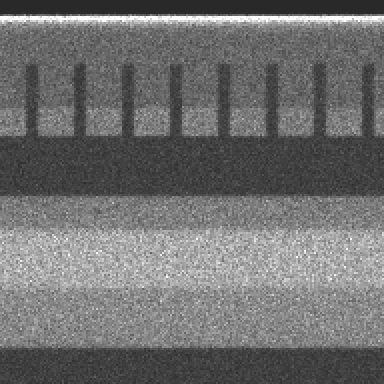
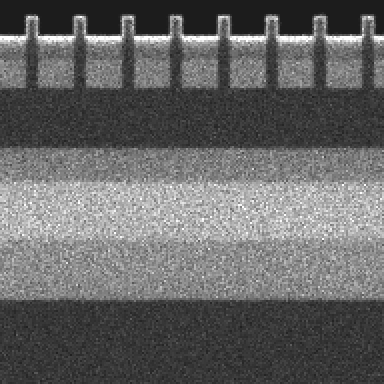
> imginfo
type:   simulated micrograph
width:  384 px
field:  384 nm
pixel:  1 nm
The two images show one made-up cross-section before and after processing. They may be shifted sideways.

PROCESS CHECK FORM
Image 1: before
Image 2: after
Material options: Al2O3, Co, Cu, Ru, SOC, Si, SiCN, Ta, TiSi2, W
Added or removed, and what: removed, SOC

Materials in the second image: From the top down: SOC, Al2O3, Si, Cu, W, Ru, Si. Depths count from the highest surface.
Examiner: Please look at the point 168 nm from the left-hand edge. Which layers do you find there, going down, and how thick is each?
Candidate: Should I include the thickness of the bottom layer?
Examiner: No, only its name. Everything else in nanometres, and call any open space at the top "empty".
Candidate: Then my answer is empty 20, SOC 24, Al2O3 28, Si 60, Cu 34, W 58, Ru 60, Si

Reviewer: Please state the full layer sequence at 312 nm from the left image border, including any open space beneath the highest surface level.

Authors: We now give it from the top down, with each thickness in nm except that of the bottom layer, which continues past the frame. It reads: empty 20, SOC 24, Al2O3 28, Si 60, Cu 34, W 58, Ru 60, Si